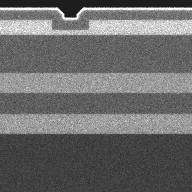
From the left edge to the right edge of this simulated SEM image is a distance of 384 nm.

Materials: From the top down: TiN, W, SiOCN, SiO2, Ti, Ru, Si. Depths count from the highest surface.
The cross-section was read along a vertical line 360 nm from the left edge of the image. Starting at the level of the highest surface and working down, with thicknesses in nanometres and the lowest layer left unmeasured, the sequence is TiN 24, W 30, SiOCN 76, SiO2 40, Ti 42, Ru 40, Si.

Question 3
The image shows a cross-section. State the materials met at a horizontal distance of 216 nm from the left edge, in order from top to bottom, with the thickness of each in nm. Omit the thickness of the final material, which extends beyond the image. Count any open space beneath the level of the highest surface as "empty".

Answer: TiN 24, W 30, SiOCN 76, SiO2 40, Ti 42, Ru 40, Si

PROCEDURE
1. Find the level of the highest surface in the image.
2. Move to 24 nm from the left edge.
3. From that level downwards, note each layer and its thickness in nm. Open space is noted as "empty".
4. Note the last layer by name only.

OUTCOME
TiN 24, W 30, SiOCN 76, SiO2 40, Ti 42, Ru 40, Si